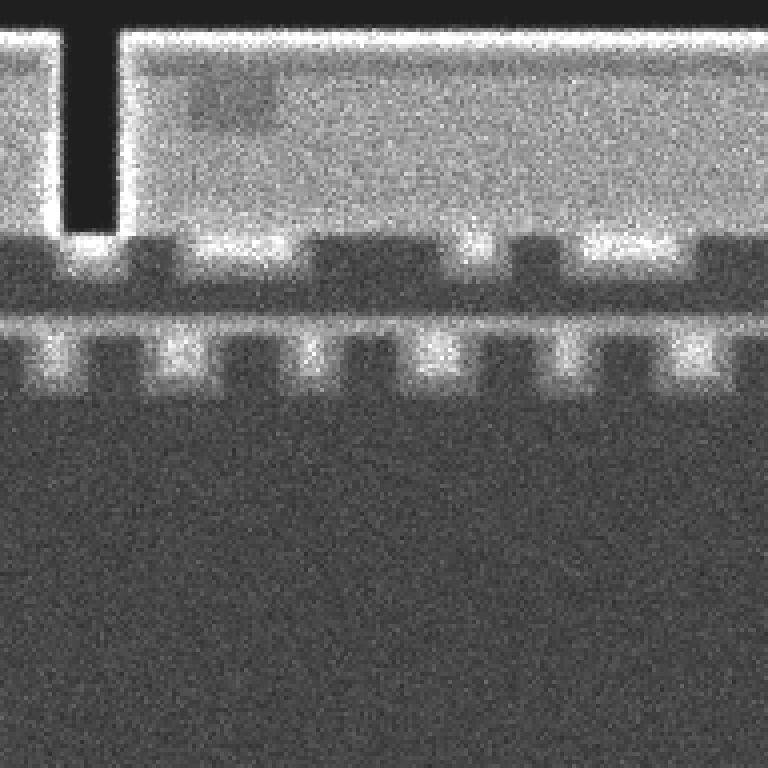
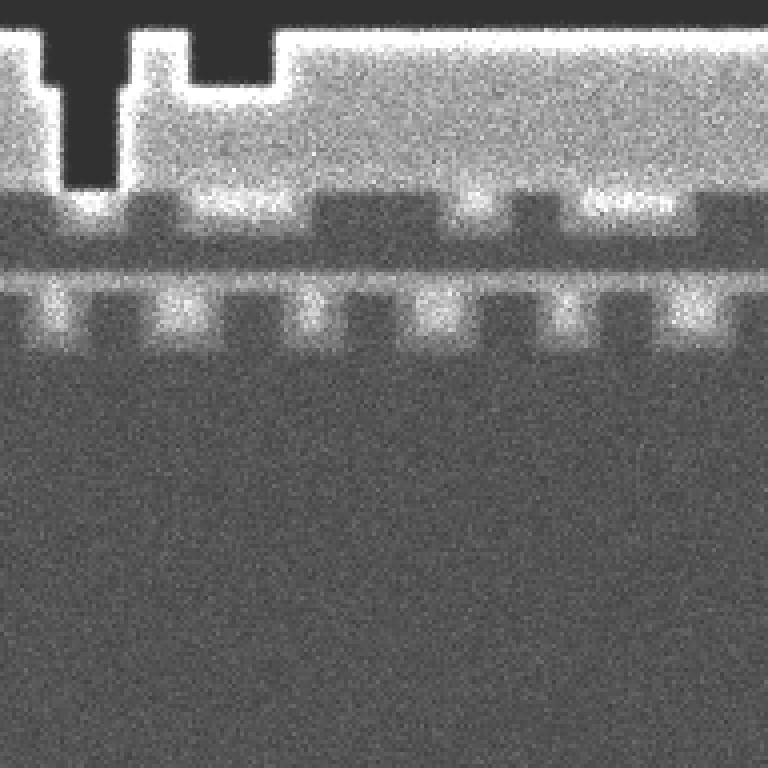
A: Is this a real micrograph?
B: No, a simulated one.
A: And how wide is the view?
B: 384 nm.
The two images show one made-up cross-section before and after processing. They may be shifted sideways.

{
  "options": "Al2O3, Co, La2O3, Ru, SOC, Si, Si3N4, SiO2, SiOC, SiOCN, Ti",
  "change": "removed",
  "material": "SOC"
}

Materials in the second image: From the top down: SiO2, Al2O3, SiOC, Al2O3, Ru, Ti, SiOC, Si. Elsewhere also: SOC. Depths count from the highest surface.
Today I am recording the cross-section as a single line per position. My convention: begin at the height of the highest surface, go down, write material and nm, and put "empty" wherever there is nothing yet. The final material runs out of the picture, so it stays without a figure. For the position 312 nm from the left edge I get SiO2 66, Al2O3 14, Ru 12, Ti 10, SiOC 18, Al2O3 10, SiOC 46, Si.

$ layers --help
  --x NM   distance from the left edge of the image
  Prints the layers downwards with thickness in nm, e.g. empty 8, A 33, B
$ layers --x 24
empty 28, SiO2 38, Al2O3 14, SiOC 40, Al2O3 10, Ru 20, Ti 10, SiOC 16, Si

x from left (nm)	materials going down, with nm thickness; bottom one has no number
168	SiO2 66, Al2O3 14, SiOC 40, Al2O3 10, Ti 30, SiOC 16, Si